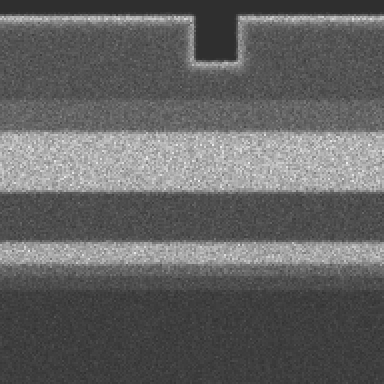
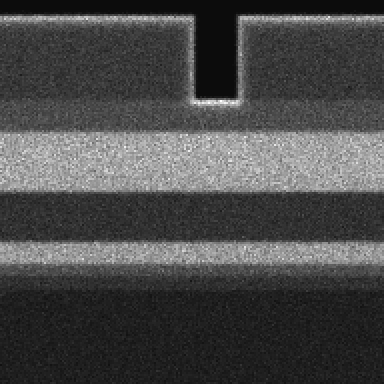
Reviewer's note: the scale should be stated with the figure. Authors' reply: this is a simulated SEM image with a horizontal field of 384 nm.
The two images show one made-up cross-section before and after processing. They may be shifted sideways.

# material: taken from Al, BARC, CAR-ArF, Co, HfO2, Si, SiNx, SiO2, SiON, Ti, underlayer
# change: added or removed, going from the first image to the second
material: underlayer
change: removed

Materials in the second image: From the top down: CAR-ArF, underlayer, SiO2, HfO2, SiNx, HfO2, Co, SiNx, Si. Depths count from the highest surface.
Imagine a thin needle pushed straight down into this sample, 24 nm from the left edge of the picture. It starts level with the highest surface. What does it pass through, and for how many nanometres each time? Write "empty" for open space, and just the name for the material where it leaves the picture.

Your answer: CAR-ArF 46, underlayer 38, SiO2 32, HfO2 60, SiNx 50, HfO2 22, Co 12, SiNx 14, Si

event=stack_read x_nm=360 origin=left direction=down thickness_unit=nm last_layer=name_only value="CAR-ArF 46, underlayer 38, SiO2 32, HfO2 60, SiNx 50, HfO2 22, Co 12, SiNx 14, Si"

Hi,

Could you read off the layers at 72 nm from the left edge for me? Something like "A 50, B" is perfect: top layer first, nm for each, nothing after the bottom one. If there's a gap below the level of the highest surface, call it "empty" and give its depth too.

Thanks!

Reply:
CAR-ArF 46, underlayer 38, SiO2 32, HfO2 60, SiNx 50, HfO2 22, Co 12, SiNx 14, Si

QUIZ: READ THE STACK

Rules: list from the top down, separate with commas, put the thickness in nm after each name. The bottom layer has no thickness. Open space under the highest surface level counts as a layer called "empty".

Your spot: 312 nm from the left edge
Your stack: CAR-ArF 46, underlayer 38, SiO2 32, HfO2 60, SiNx 50, HfO2 22, Co 12, SiNx 14, Si